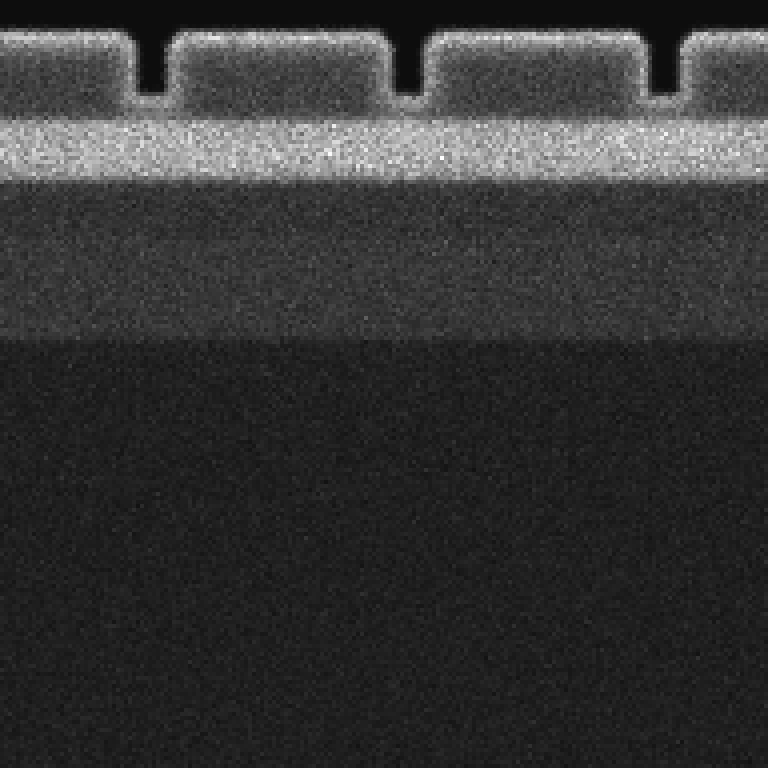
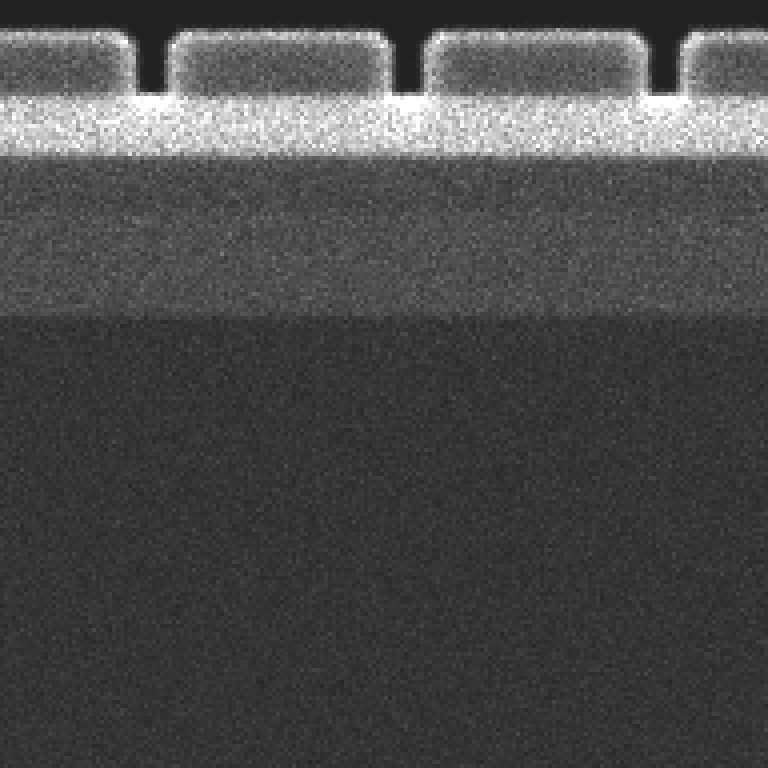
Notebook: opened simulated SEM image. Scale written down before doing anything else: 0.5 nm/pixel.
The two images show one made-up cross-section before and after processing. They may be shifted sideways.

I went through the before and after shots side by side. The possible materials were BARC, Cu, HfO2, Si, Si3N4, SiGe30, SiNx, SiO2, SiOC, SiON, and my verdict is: removed, SiO2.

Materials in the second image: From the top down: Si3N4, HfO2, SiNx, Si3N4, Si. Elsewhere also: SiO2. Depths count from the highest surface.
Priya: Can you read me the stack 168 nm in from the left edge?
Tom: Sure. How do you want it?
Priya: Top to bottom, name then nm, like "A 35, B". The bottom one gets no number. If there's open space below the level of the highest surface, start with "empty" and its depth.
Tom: Si3N4 32, HfO2 30, SiNx 28, Si3N4 52, Si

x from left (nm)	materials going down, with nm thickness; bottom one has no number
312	SiO2 32, HfO2 30, SiNx 28, Si3N4 52, Si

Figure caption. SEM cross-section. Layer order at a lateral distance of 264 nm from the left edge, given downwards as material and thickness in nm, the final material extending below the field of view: Si3N4 32, HfO2 30, SiNx 28, Si3N4 52, Si